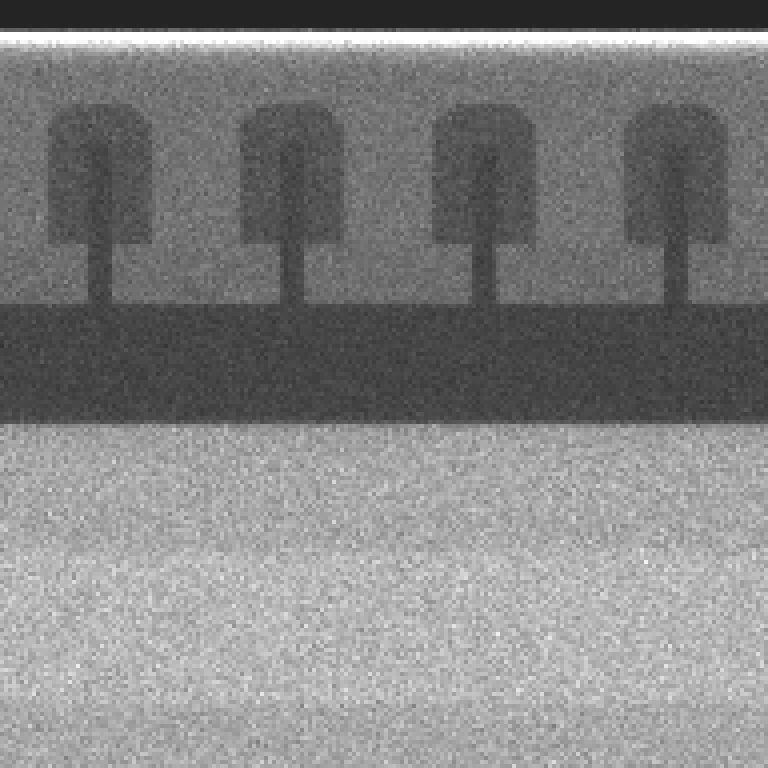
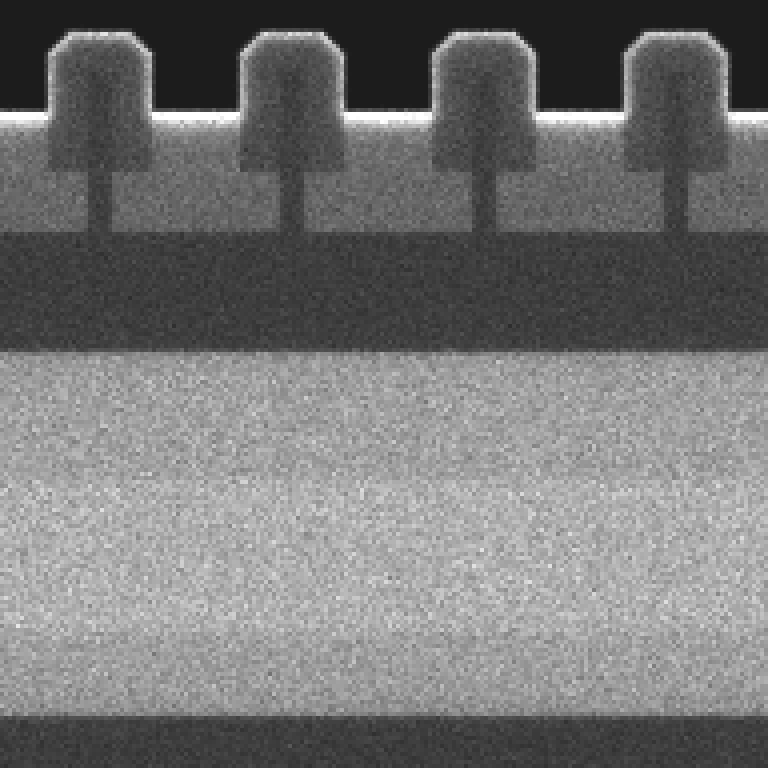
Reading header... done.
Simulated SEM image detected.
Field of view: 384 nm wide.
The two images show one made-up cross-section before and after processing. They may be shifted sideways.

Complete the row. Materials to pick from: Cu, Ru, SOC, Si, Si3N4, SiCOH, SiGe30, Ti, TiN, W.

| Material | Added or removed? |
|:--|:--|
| SOC | removed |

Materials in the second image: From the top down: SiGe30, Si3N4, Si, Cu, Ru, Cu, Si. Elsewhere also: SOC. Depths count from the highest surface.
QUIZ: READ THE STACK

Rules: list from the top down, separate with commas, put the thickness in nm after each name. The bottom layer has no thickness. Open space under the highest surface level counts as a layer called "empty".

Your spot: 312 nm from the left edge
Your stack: empty 10, SiGe30 60, Si3N4 30, Si 60, Cu 64, Ru 76, Cu 42, Si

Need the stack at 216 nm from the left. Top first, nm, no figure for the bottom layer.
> empty 10, SiGe30 60, Si3N4 30, Si 60, Cu 64, Ru 76, Cu 42, Si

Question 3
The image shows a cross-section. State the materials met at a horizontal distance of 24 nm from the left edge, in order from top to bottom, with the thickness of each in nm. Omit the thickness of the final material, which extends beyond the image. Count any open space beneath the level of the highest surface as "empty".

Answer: empty 10, SiGe30 60, Si3N4 30, Si 60, Cu 64, Ru 76, Cu 42, Si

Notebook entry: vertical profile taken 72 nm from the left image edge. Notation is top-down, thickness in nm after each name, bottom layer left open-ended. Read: empty 8, SiGe30 62, Si3N4 30, Si 60, Cu 64, Ru 76, Cu 42, Si